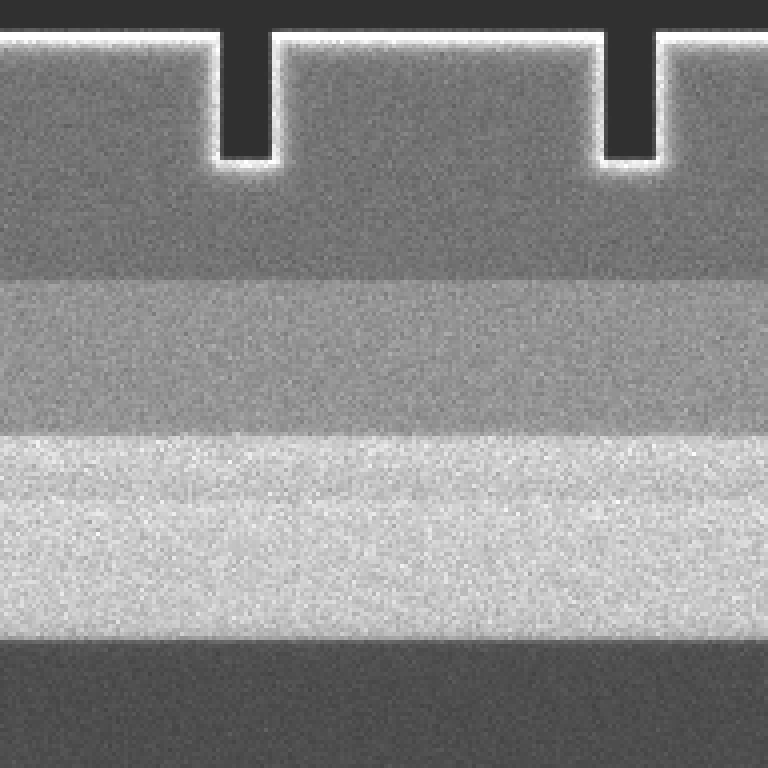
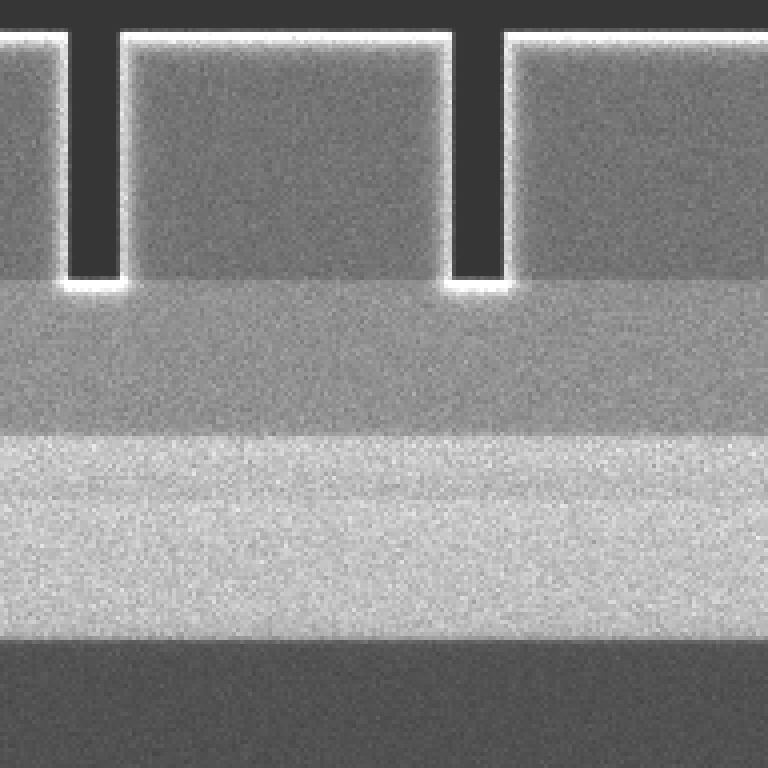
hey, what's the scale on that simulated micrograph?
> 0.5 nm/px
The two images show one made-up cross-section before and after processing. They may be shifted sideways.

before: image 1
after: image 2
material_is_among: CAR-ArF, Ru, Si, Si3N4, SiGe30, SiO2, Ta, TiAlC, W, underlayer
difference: underlayer, removed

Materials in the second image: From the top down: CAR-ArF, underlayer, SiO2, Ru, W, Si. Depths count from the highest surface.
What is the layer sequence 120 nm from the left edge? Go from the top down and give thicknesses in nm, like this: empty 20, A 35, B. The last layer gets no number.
CAR-ArF 64, underlayer 60, SiO2 78, Ru 32, W 70, Si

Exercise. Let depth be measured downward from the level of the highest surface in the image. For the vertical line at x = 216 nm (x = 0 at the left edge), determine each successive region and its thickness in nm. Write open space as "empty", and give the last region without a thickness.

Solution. CAR-ArF 64, underlayer 60, SiO2 78, Ru 32, W 70, Si